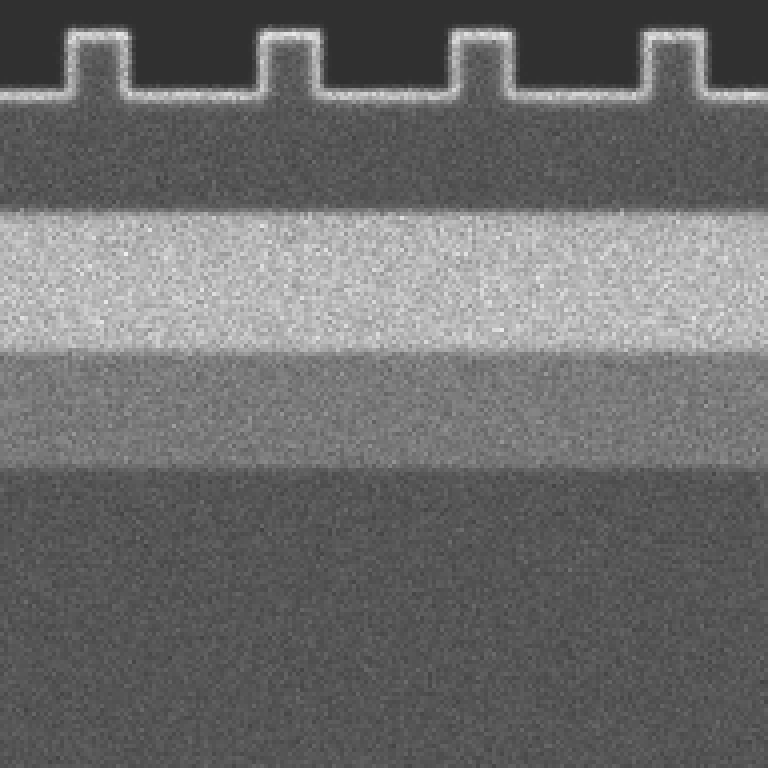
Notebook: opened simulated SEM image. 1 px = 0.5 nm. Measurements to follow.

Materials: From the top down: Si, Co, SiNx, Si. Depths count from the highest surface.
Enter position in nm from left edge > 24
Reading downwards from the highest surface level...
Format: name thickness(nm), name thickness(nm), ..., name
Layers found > empty 30, Si 60, Co 70, SiNx 58, Si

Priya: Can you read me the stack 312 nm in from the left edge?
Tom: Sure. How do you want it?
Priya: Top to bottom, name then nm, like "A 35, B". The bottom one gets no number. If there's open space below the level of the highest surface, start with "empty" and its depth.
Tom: empty 30, Si 60, Co 70, SiNx 58, Si